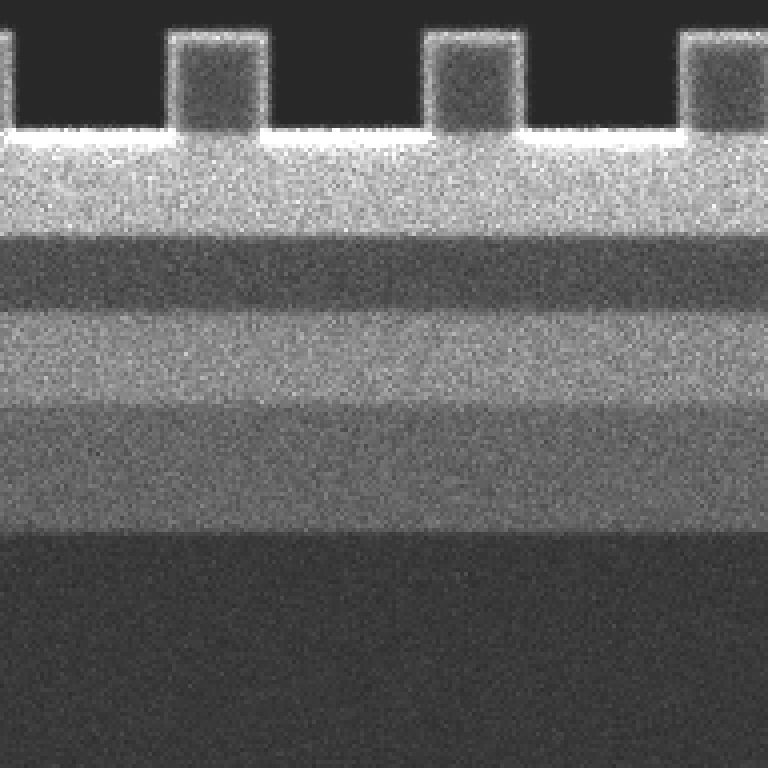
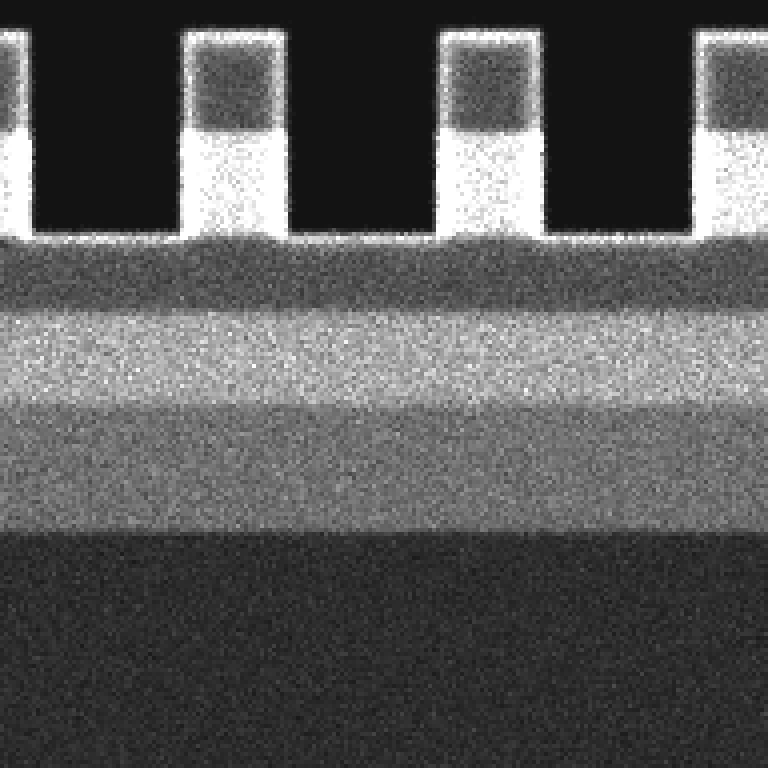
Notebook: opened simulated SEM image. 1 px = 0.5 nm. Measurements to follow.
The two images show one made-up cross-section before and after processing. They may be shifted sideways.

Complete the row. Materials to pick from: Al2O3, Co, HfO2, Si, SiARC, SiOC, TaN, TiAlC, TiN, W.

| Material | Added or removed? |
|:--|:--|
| HfO2 | removed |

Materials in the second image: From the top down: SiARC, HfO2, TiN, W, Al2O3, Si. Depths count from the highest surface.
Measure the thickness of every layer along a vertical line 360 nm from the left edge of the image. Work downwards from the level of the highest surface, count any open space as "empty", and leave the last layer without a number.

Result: SiARC 50, HfO2 52, TiN 38, W 46, Al2O3 64, Si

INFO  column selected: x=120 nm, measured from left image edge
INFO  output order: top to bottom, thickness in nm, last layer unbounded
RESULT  SiARC 50, HfO2 52, TiN 38, W 46, Al2O3 64, Si